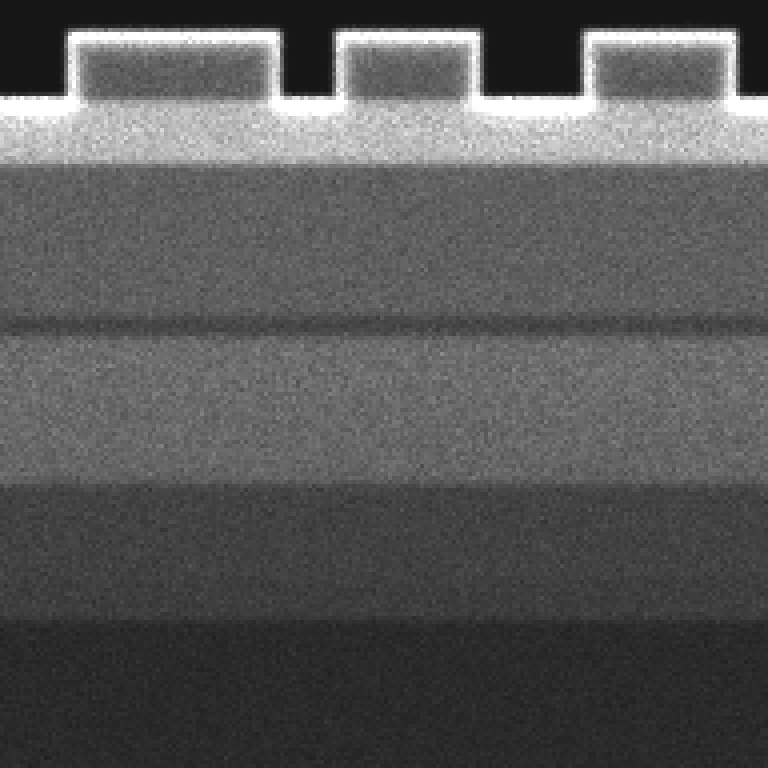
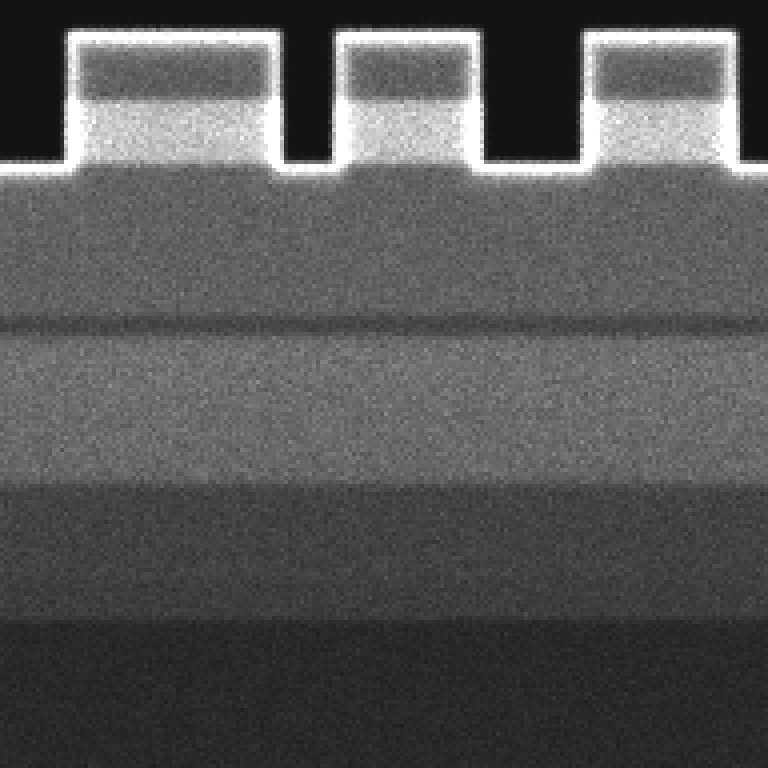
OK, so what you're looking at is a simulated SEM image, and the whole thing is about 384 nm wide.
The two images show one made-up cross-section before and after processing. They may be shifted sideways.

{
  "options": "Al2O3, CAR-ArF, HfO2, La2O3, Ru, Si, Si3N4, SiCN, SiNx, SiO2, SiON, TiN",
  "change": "removed",
  "material": "HfO2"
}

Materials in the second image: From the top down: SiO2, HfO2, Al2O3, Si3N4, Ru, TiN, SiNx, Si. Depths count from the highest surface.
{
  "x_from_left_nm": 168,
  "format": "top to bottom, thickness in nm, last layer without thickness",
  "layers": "SiO2 34, HfO2 32, Al2O3 76, Si3N4 10, Ru 74, TiN 48, SiNx 20, Si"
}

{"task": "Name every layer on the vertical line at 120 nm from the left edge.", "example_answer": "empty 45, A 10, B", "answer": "SiO2 34, HfO2 32, Al2O3 76, Si3N4 10, Ru 74, TiN 48, SiNx 20, Si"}